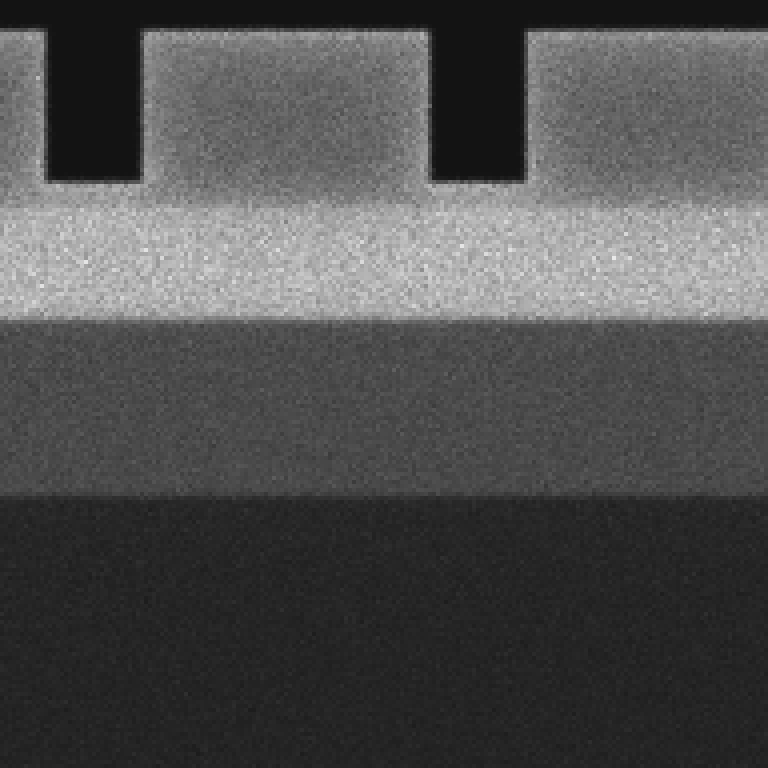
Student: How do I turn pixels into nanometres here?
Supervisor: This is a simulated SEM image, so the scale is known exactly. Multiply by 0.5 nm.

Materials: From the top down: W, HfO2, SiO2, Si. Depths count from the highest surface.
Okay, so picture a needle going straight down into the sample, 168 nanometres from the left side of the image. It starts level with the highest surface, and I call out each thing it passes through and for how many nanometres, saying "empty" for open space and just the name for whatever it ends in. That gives W 88, HfO2 56, SiO2 88, Si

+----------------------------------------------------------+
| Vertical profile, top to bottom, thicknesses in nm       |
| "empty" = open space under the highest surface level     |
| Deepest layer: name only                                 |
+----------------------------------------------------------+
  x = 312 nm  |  W 88, HfO2 56, SiO2 88, Si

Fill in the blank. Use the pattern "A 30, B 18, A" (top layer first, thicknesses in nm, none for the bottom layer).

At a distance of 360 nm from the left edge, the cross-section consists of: W 88, HfO2 56, SiO2 88, Si